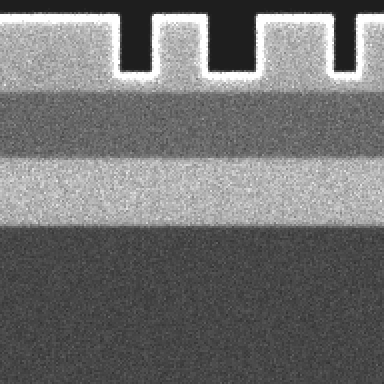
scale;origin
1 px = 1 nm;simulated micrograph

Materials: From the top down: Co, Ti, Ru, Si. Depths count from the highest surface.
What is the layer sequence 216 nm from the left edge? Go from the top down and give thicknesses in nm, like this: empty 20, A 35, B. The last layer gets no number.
empty 58, Co 18, Ti 66, Ru 68, Si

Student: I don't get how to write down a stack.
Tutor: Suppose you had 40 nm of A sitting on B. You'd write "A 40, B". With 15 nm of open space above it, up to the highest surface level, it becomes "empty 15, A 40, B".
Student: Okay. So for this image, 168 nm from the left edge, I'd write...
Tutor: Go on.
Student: Co 76, Ti 66, Ru 68, Si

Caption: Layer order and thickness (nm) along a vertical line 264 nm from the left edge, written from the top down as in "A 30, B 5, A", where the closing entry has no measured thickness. Co 76, Ti 66, Ru 68, Si